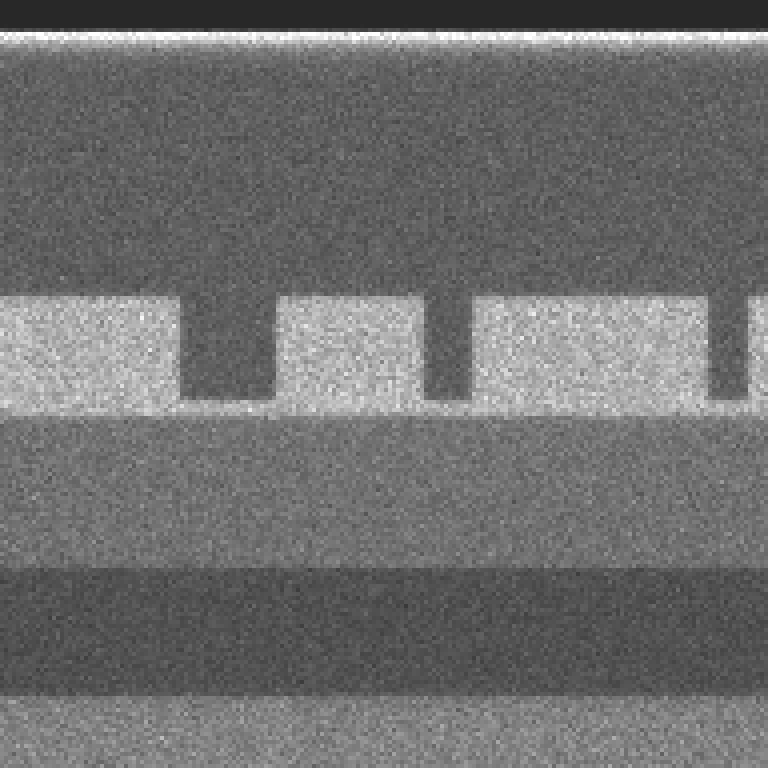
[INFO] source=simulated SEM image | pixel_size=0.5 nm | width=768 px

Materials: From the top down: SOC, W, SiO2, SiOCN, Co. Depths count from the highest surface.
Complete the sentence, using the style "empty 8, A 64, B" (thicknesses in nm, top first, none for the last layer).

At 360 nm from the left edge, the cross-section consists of SOC 184, W 8, SiO2 76, SiOCN 64, Co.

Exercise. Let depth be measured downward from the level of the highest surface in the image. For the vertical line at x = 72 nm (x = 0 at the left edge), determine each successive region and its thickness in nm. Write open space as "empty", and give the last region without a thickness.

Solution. SOC 132, W 60, SiO2 76, SiOCN 64, Co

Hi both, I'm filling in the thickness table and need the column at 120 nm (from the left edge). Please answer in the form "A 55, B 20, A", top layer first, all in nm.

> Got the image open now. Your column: SOC 184, W 8, SiO2 76, SiOCN 64, Co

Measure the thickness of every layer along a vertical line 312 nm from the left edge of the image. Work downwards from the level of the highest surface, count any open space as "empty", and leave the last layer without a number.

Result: SOC 132, W 60, SiO2 76, SiOCN 64, Co